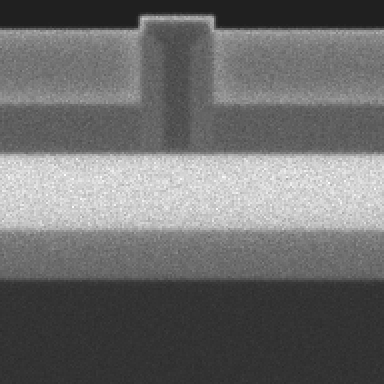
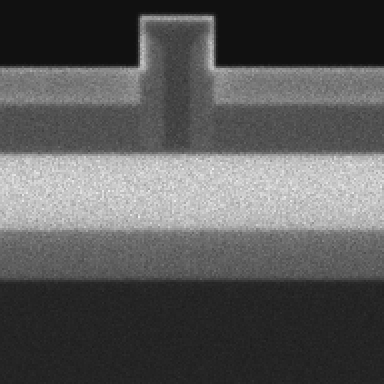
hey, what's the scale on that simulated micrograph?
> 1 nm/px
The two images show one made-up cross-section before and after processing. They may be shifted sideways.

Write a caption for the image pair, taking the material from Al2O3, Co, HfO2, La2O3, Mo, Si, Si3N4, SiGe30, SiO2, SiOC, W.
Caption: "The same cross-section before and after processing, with W removed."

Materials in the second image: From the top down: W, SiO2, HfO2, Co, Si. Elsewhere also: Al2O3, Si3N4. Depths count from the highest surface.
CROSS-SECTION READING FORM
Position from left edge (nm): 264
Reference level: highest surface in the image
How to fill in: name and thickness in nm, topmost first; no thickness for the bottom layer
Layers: empty 52, W 36, SiO2 50, HfO2 76, Co 50, Si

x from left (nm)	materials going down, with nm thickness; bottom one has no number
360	empty 52, W 36, SiO2 50, HfO2 76, Co 50, Si